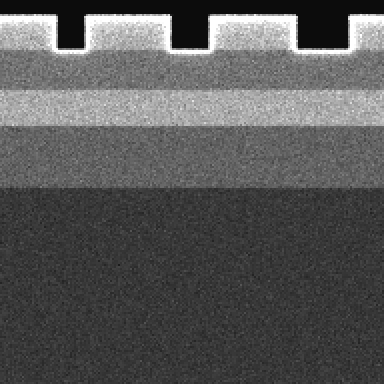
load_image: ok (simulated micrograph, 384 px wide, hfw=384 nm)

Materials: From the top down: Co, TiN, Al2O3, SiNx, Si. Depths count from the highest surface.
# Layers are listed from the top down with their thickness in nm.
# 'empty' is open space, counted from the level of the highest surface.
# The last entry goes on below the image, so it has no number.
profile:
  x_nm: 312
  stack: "empty 34, TiN 40, Al2O3 36, SiNx 62, Si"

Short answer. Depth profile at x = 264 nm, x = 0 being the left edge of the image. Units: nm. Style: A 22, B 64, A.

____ Co 34, TiN 40, Al2O3 36, SiNx 62, Si